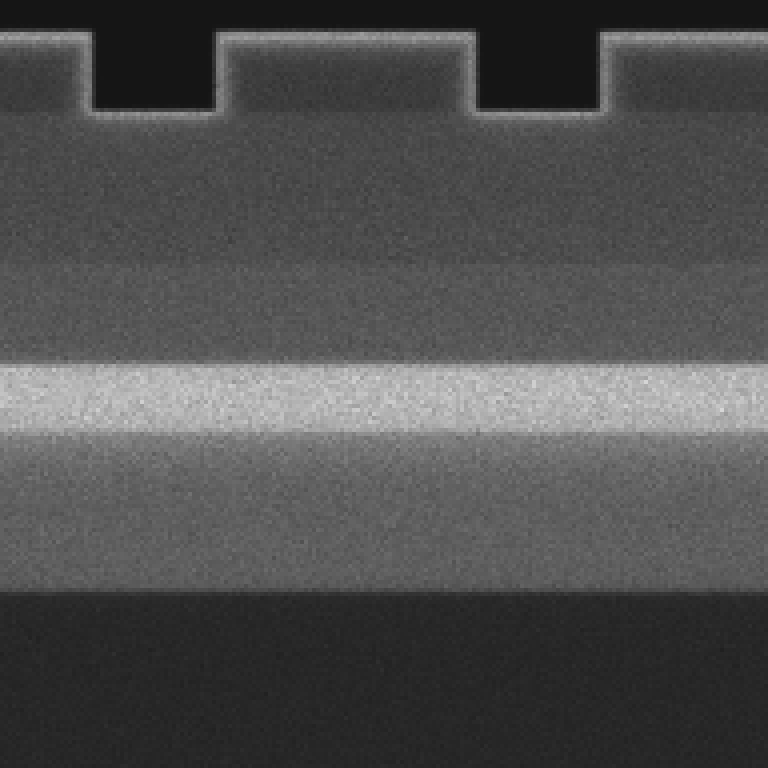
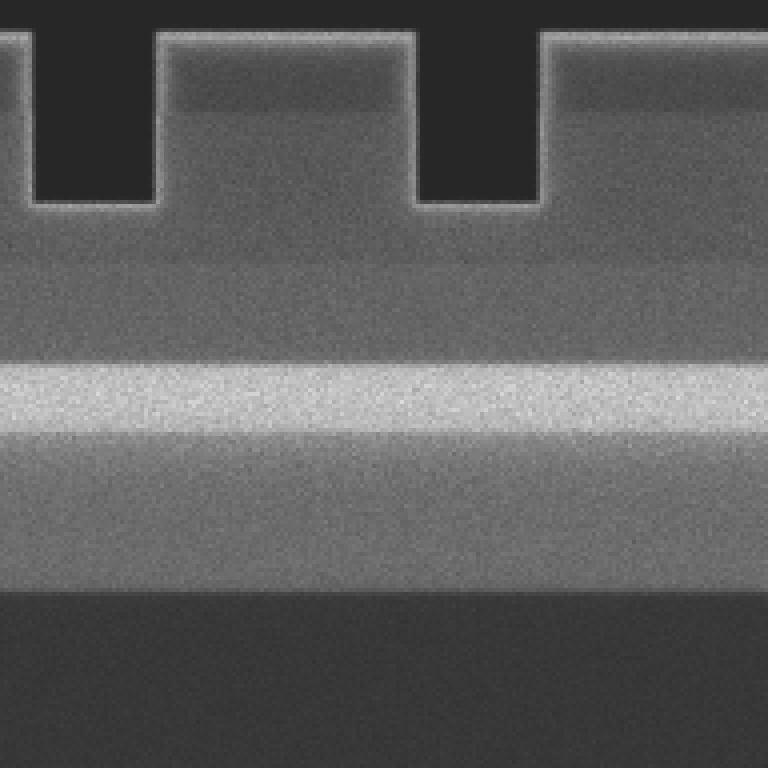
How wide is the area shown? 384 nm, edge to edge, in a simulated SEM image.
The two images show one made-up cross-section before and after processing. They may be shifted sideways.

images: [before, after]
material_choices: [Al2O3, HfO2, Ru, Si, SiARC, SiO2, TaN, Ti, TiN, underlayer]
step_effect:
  removed: TiN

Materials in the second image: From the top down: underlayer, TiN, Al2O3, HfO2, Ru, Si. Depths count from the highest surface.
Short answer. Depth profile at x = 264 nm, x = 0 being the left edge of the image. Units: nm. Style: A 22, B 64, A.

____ empty 86, TiN 30, Al2O3 50, HfO2 34, Ru 80, Si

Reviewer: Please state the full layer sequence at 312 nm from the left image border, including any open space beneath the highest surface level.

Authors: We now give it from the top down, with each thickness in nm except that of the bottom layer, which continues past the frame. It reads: underlayer 40, TiN 76, Al2O3 50, HfO2 34, Ru 80, Si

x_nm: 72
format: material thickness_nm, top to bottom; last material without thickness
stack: empty 86, TiN 30, Al2O3 50, HfO2 34, Ru 80, Si